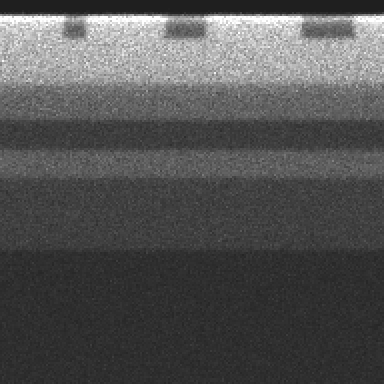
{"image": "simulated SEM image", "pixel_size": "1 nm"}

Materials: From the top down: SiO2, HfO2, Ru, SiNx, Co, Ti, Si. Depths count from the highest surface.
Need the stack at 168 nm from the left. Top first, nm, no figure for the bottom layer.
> SiO2 22, HfO2 46, Ru 36, SiNx 30, Co 28, Ti 72, Si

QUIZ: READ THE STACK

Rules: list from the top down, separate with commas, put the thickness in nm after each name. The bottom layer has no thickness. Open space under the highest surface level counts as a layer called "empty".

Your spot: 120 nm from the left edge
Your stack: HfO2 68, Ru 36, SiNx 30, Co 28, Ti 72, Si